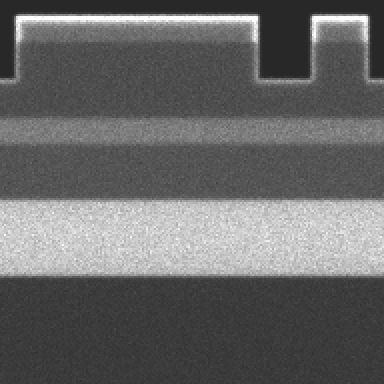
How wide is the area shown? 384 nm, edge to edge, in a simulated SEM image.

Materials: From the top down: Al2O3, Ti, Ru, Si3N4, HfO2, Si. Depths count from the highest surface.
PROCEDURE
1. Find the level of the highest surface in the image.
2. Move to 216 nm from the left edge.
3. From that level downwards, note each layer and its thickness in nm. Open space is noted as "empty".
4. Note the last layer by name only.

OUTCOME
Al2O3 26, Ti 76, Ru 26, Si3N4 56, HfO2 76, Si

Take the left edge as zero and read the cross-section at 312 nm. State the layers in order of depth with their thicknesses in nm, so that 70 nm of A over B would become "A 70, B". Al2O3 26, Ti 76, Ru 26, Si3N4 56, HfO2 76, Si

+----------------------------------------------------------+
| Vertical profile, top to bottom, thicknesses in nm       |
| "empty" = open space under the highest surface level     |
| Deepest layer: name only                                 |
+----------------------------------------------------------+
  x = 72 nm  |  Al2O3 26, Ti 76, Ru 26, Si3N4 56, HfO2 76, Si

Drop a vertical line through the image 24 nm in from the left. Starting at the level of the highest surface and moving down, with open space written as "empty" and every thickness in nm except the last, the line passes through Al2O3 26, Ti 76, Ru 26, Si3N4 56, HfO2 76, Si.